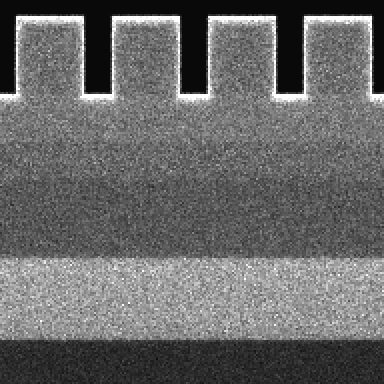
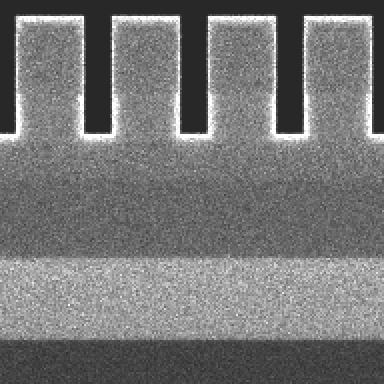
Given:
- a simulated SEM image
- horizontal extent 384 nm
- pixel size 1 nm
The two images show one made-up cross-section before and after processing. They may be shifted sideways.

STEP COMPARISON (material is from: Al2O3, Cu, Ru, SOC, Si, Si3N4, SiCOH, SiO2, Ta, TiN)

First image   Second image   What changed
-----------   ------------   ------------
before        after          SiO2, removed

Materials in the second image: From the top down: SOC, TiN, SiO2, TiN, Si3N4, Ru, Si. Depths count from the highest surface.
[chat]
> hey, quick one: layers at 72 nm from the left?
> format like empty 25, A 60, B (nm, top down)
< SOC 16, TiN 62, SiO2 48, TiN 38, Si3N4 78, Ru 82, Si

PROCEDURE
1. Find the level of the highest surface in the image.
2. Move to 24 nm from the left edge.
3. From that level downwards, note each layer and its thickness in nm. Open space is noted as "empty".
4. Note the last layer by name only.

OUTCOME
SOC 16, TiN 62, SiO2 48, TiN 38, Si3N4 78, Ru 82, Si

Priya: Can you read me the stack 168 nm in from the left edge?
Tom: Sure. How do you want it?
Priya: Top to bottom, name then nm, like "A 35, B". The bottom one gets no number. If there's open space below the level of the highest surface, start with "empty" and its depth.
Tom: SOC 16, TiN 62, SiO2 48, TiN 38, Si3N4 78, Ru 82, Si